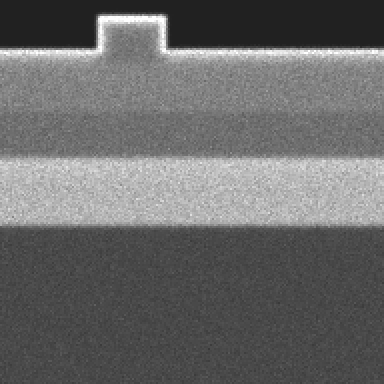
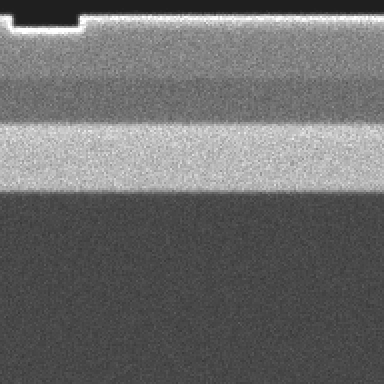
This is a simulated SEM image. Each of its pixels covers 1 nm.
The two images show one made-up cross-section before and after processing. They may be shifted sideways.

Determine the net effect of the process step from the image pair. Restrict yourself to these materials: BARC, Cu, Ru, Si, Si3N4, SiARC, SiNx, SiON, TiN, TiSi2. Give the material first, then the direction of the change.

SiARC: removed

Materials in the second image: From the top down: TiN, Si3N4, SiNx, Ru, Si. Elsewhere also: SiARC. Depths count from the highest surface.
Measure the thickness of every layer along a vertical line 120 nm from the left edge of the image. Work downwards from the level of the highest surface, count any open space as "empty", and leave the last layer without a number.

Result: TiN 12, Si3N4 50, SiNx 46, Ru 68, Si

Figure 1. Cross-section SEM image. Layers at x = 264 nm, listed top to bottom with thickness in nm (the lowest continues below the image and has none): TiN 12, Si3N4 50, SiNx 46, Ru 68, Si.